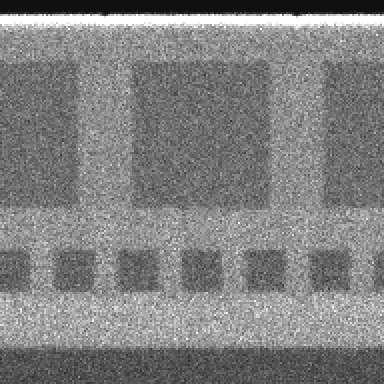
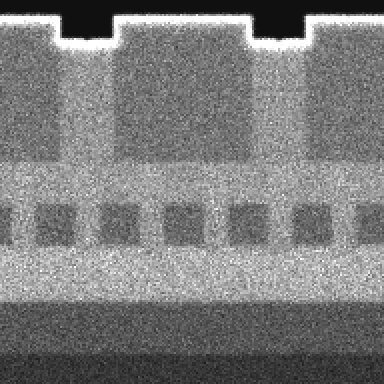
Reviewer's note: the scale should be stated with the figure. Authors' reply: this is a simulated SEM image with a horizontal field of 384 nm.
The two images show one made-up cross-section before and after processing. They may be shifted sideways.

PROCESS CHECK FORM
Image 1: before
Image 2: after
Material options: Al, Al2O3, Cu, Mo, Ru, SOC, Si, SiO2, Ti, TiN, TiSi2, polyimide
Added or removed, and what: removed, SiO2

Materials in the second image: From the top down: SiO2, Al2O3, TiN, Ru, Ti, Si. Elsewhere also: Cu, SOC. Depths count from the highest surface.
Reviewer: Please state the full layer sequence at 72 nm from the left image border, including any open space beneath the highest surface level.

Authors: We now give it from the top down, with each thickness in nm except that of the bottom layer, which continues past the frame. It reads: empty 24, SiO2 122, Al2O3 42, TiN 42, Ru 56, Ti 52, Si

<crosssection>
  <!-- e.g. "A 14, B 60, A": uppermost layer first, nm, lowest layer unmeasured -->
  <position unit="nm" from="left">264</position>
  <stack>empty 24, SiO2 122, Al2O3 42, TiN 42, Ru 56, Ti 52, Si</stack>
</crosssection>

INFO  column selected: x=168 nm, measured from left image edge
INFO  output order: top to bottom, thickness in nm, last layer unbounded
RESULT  SOC 146, Al2O3 42, TiN 42, Ru 56, Ti 52, Si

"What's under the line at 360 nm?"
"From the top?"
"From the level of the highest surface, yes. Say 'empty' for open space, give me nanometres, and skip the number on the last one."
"SOC 146, Al2O3 42, TiN 42, Ru 56, Ti 52, Si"